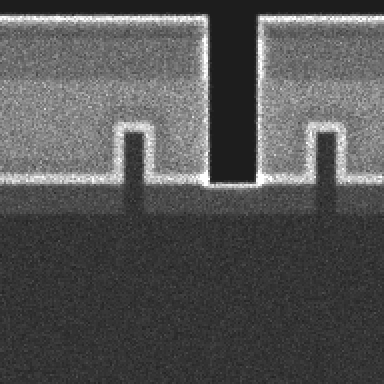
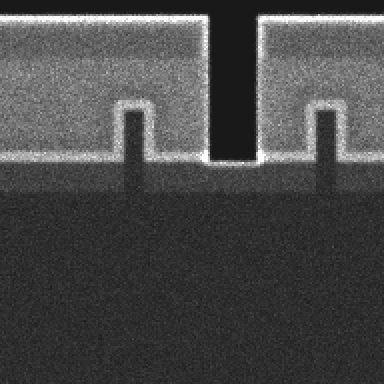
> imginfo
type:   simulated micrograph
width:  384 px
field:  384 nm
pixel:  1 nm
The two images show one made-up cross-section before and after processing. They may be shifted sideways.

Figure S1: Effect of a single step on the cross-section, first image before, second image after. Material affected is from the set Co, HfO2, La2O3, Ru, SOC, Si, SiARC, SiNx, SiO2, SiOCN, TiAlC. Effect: removed SOC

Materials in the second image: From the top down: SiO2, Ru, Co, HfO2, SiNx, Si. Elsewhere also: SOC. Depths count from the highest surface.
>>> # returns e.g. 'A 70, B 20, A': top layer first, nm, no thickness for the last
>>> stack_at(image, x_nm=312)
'SiO2 42, Ru 28, Co 14, HfO2 62, SiNx 30, Si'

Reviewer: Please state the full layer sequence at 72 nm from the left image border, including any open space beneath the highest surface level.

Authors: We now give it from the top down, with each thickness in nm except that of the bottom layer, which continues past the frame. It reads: SiO2 42, Ru 80, Co 14, HfO2 10, SiNx 30, Si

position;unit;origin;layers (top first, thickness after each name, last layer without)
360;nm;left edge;SiO2 42, Ru 80, Co 14, HfO2 10, SiNx 30, Si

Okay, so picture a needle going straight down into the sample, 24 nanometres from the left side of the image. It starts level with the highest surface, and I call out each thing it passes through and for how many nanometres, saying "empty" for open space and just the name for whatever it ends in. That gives SiO2 42, Ru 80, Co 14, HfO2 10, SiNx 30, Si